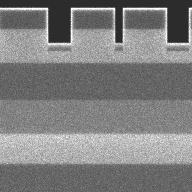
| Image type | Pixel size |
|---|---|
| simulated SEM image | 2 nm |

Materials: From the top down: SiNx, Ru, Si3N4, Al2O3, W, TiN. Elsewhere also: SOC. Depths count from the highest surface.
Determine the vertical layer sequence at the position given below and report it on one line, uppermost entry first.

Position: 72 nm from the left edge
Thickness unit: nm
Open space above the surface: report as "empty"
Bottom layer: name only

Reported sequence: SiNx 42, Ru 68, Si3N4 74, Al2O3 68, W 60, TiN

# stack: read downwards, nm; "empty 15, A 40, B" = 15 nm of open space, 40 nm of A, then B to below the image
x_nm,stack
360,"empty 70, SOC 16, Ru 24, Si3N4 74, Al2O3 68, W 60, TiN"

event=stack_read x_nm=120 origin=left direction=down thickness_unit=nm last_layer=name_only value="empty 70, SOC 16, Ru 24, Si3N4 74, Al2O3 68, W 60, TiN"